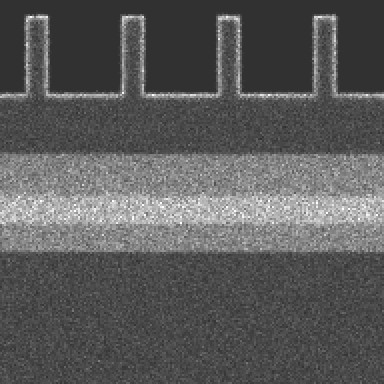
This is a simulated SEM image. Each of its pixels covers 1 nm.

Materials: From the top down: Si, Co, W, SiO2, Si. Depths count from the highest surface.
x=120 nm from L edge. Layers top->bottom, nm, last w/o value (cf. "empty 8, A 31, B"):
empty 78, Si 60, Co 42, W 28, SiO2 28, Si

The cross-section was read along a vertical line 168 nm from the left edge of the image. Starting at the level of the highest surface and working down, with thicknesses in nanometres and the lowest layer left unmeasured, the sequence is empty 78, Si 60, Co 42, W 28, SiO2 28, Si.